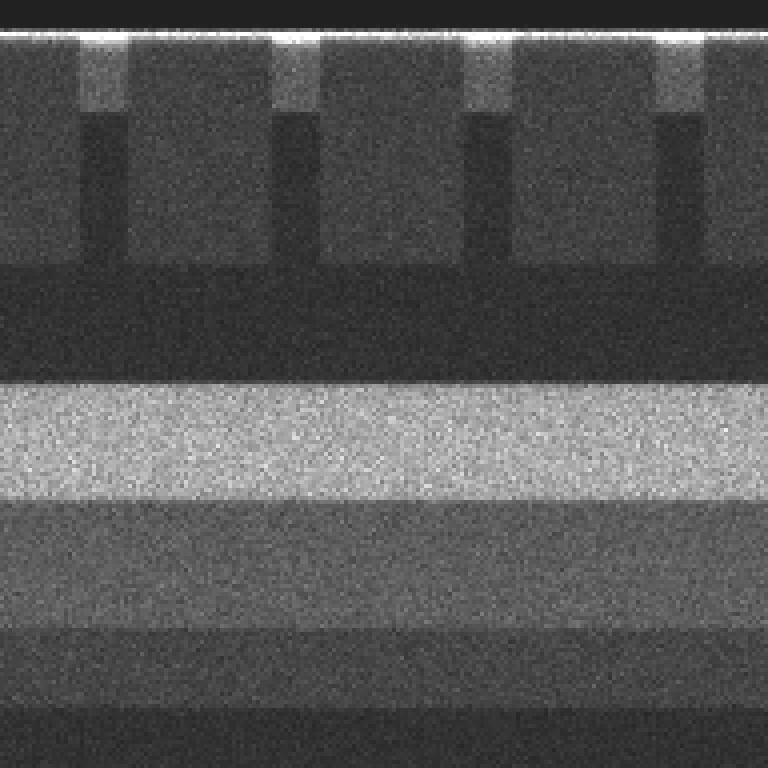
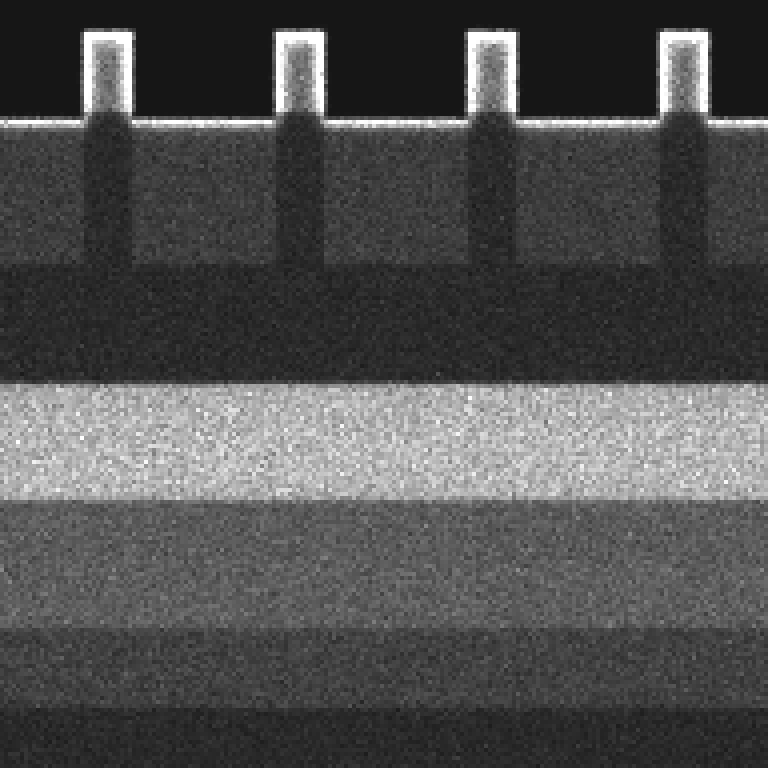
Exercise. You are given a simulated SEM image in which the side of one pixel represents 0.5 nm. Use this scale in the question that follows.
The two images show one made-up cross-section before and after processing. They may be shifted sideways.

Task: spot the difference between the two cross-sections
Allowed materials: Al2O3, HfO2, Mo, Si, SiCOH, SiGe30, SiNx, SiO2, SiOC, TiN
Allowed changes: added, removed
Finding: removed SiNx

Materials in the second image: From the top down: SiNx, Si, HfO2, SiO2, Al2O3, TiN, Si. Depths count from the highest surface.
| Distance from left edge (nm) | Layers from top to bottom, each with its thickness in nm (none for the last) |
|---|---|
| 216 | empty 44, SiNx 72, Si 60, HfO2 58, SiO2 30, Al2O3 34, TiN 40, Si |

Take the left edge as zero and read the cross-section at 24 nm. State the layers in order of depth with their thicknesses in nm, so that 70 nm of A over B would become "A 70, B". empty 44, SiNx 72, Si 60, HfO2 58, SiO2 30, Al2O3 34, TiN 40, Si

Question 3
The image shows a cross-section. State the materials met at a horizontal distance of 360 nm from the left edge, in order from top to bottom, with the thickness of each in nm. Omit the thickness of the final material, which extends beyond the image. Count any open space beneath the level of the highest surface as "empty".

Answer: empty 44, SiNx 72, Si 60, HfO2 58, SiO2 30, Al2O3 34, TiN 40, Si